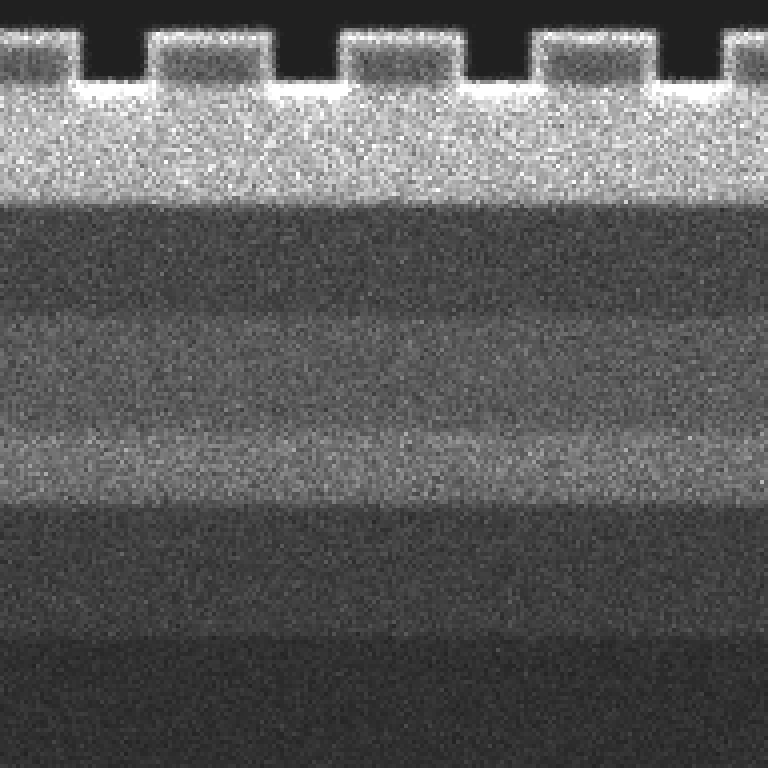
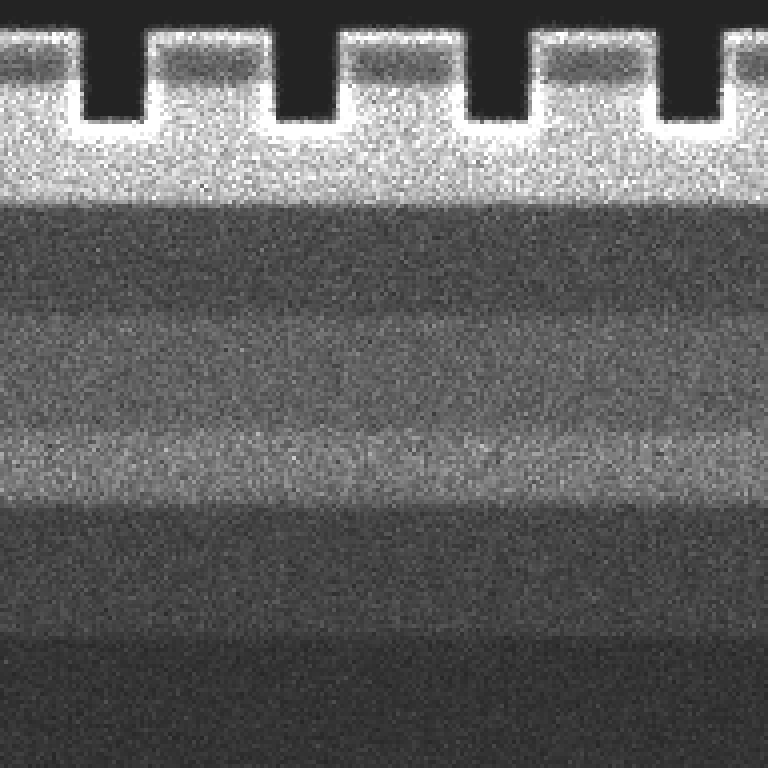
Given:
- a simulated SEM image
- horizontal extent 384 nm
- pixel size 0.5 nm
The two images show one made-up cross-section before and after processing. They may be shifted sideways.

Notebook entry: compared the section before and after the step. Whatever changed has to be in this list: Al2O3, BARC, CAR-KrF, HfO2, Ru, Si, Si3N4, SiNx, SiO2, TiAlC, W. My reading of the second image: HfO2 removed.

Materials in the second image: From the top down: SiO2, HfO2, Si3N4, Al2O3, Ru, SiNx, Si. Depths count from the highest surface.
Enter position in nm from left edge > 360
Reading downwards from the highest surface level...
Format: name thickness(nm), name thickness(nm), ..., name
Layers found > empty 46, HfO2 40, Si3N4 56, Al2O3 58, Ru 36, SiNx 66, Si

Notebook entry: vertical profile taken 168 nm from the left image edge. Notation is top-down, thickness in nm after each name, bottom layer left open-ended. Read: empty 46, HfO2 40, Si3N4 56, Al2O3 58, Ru 36, SiNx 66, Si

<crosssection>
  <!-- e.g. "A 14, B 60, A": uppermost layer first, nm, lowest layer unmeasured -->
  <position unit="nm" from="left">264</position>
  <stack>empty 46, HfO2 40, Si3N4 56, Al2O3 58, Ru 36, SiNx 66, Si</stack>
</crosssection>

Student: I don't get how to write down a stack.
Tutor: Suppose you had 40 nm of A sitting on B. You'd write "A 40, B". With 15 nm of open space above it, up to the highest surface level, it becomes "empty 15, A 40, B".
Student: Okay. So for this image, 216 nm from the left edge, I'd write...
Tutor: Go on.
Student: SiO2 26, HfO2 60, Si3N4 56, Al2O3 58, Ru 36, SiNx 66, Si